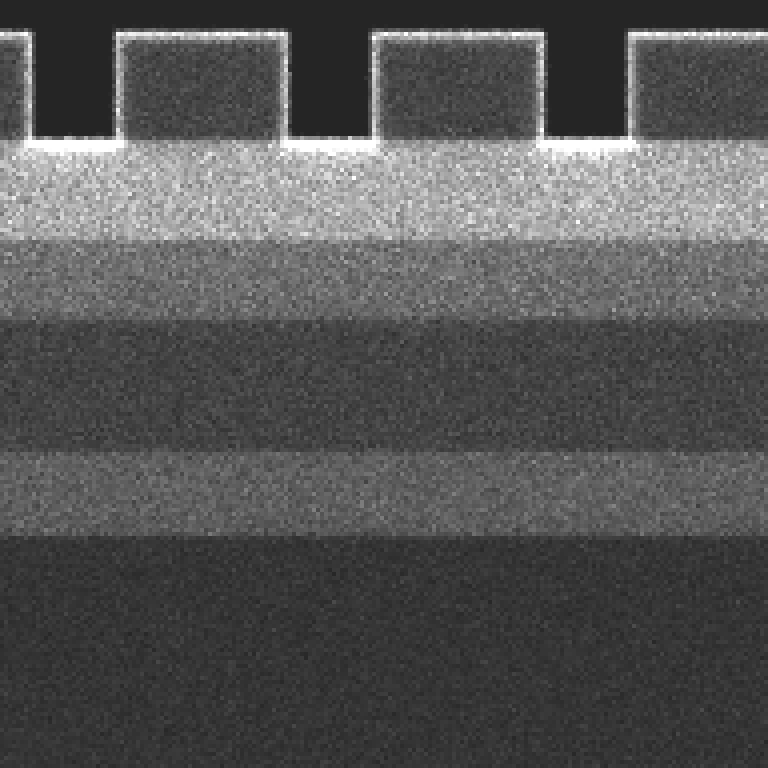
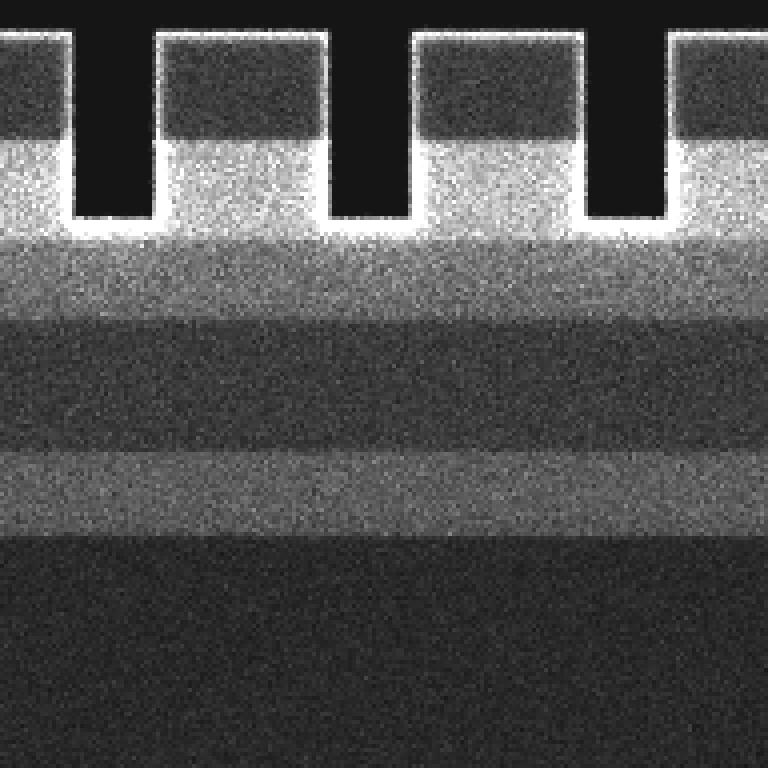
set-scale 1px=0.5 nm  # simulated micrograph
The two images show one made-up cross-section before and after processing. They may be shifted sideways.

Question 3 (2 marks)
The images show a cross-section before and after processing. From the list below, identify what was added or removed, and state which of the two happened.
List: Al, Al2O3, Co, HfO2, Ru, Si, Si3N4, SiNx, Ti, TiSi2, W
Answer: HfO2 was removed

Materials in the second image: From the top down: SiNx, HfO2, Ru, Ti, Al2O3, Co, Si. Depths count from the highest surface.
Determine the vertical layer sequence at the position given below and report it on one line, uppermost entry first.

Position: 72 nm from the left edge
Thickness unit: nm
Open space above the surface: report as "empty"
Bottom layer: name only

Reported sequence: empty 94, HfO2 10, Ru 40, Ti 66, Al2O3 32, Co 10, Si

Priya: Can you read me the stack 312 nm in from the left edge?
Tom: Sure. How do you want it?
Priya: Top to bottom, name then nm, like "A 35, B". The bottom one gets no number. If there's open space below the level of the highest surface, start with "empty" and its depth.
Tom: empty 94, HfO2 10, Ru 40, Ti 66, Al2O3 32, Co 10, Si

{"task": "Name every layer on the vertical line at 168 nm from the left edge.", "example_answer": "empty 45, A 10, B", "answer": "empty 94, HfO2 10, Ru 40, Ti 66, Al2O3 32, Co 10, Si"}